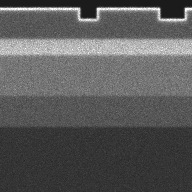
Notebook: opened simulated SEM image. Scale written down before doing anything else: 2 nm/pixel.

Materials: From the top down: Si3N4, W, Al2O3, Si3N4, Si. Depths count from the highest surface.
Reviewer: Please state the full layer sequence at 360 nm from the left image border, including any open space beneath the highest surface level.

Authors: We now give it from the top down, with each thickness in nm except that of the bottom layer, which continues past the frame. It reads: empty 22, Si3N4 40, W 32, Al2O3 82, Si3N4 62, Si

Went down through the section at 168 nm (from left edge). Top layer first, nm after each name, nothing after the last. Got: empty 22, Si3N4 40, W 32, Al2O3 82, Si3N4 62, Si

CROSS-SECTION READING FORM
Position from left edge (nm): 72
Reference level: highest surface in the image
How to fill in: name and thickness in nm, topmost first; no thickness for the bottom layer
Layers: Si3N4 62, W 32, Al2O3 82, Si3N4 62, Si